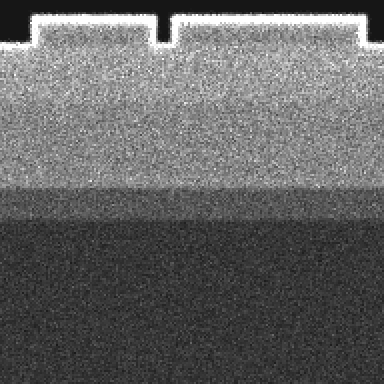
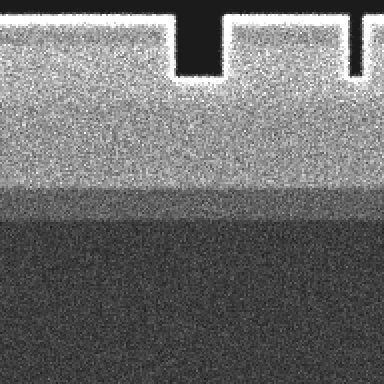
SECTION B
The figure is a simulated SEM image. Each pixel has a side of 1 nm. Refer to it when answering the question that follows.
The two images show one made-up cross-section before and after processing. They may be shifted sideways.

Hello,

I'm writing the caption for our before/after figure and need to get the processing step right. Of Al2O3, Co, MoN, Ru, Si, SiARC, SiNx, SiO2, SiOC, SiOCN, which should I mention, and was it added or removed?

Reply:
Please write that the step removed Ru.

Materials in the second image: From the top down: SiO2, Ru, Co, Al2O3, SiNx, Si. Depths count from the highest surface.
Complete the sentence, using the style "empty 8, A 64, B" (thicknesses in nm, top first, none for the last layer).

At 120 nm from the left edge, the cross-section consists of SiO2 28, Ru 58, Co 74, Al2O3 12, SiNx 32, Si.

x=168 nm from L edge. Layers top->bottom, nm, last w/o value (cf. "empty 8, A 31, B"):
SiO2 28, Ru 58, Co 74, Al2O3 12, SiNx 32, Si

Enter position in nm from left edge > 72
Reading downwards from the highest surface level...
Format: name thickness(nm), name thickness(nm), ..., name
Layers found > SiO2 28, Ru 58, Co 74, Al2O3 12, SiNx 32, Si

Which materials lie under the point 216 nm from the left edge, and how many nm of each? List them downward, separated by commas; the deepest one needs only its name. empty 62, Ru 24, Co 74, Al2O3 12, SiNx 32, Si